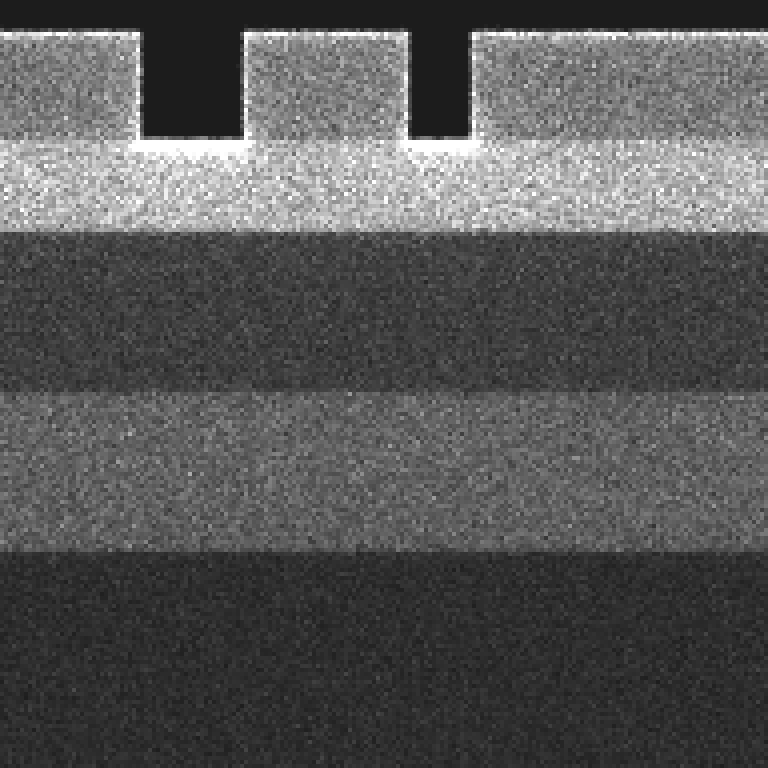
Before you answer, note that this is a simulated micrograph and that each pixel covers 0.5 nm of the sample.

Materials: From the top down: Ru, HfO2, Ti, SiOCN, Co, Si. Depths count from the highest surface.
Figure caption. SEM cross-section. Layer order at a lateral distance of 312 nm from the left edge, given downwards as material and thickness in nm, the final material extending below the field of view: Ru 54, HfO2 46, Ti 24, SiOCN 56, Co 80, Si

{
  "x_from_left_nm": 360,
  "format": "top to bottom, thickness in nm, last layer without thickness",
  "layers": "Ru 54, HfO2 46, Ti 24, SiOCN 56, Co 80, Si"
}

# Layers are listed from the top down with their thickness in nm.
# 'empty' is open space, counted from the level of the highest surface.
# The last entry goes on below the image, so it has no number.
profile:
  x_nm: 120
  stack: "empty 54, HfO2 46, Ti 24, SiOCN 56, Co 80, Si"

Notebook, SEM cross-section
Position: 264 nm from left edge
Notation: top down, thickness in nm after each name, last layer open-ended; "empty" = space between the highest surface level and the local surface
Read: Ru 54, HfO2 46, Ti 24, SiOCN 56, Co 80, Si